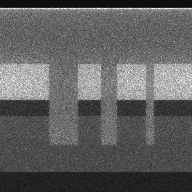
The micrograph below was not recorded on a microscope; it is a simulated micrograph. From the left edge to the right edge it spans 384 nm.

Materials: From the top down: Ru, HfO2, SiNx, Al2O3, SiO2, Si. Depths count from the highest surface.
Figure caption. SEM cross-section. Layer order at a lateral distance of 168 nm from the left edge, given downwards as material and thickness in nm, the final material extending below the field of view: Ru 112, HfO2 72, SiNx 32, Al2O3 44, SiO2 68, Si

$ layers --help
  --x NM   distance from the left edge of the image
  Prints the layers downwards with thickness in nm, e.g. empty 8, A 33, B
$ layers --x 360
Ru 112, HfO2 72, SiNx 32, Al2O3 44, SiO2 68, Si